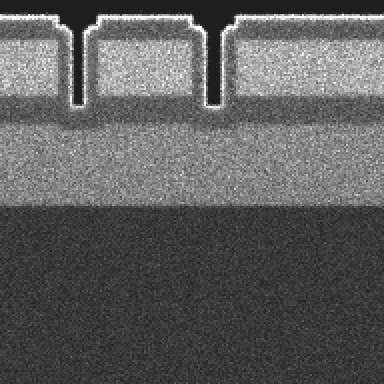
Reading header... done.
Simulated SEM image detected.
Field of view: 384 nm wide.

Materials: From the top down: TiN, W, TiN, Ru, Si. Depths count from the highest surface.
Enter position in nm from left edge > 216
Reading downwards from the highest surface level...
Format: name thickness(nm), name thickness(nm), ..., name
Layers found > empty 90, TiN 24, Ru 76, Si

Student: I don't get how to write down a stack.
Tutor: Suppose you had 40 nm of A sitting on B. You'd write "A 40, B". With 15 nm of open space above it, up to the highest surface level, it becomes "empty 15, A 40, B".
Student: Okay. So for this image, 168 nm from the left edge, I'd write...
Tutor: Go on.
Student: TiN 24, W 56, TiN 28, Ru 82, Si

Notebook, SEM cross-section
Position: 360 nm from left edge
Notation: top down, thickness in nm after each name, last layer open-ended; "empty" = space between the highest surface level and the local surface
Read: TiN 24, W 56, TiN 28, Ru 82, Si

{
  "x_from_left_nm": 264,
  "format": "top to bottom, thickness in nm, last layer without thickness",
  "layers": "TiN 24, W 56, TiN 28, Ru 82, Si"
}